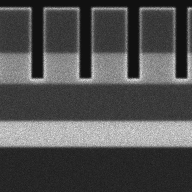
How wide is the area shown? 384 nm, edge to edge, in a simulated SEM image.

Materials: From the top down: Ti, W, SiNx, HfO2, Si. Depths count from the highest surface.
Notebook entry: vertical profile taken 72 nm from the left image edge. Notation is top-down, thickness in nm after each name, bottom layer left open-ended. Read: empty 142, W 10, SiNx 74, HfO2 52, Si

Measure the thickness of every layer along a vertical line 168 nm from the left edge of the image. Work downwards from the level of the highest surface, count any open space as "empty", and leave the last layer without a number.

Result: empty 142, W 10, SiNx 74, HfO2 52, Si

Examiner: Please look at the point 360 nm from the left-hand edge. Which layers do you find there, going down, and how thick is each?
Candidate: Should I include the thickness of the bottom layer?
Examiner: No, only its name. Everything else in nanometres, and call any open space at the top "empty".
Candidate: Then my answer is empty 142, W 10, SiNx 74, HfO2 52, Si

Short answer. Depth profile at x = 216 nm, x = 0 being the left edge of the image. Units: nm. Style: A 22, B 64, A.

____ Ti 90, W 62, SiNx 74, HfO2 52, Si